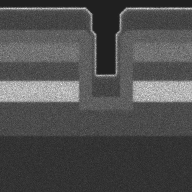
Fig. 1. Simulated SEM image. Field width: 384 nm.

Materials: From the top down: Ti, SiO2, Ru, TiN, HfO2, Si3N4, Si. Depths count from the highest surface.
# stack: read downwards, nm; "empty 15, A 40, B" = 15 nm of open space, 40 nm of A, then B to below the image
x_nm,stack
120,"Ti 44, SiO2 26, Ru 38, TiN 38, HfO2 42, Si3N4 68, Si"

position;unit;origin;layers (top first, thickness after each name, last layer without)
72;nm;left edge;Ti 44, SiO2 26, Ru 38, TiN 38, HfO2 42, Si3N4 68, Si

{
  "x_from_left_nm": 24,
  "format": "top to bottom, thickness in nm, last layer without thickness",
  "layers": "Ti 44, SiO2 26, Ru 38, TiN 38, HfO2 42, Si3N4 68, Si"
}